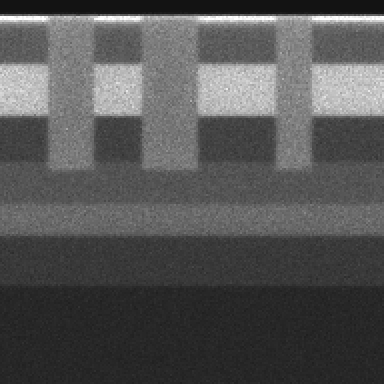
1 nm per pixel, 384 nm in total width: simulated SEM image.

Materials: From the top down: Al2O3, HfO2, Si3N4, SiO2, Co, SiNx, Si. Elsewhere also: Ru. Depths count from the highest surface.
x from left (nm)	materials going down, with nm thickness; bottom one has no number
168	Ru 154, SiO2 34, Co 32, SiNx 50, Si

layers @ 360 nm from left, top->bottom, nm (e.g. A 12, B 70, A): Al2O3 48, HfO2 52, Si3N4 46, SiO2 42, Co 32, SiNx 50, Si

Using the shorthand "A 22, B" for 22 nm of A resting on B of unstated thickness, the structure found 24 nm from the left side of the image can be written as Al2O3 48, HfO2 52, Si3N4 46, SiO2 42, Co 32, SiNx 50, Si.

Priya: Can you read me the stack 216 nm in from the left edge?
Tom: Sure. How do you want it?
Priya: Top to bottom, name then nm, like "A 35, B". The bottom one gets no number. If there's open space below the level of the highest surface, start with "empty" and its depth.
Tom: Al2O3 48, HfO2 52, Si3N4 46, SiO2 42, Co 32, SiNx 50, Si